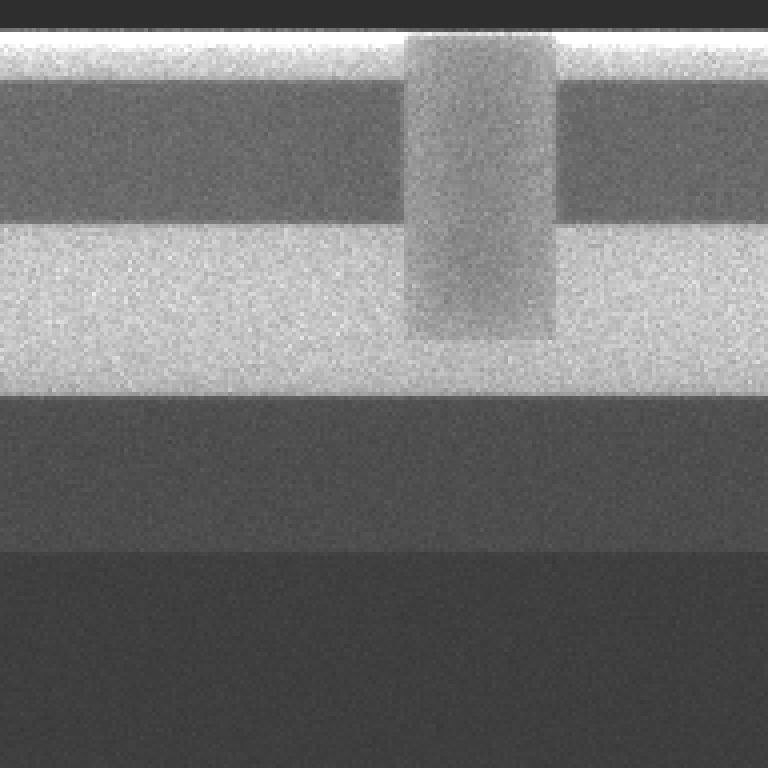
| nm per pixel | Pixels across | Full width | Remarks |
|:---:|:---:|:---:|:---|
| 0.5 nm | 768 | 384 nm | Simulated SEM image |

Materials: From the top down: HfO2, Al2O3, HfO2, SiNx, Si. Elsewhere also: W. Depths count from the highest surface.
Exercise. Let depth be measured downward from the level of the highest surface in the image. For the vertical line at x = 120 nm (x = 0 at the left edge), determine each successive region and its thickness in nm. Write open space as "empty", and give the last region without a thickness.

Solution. HfO2 24, Al2O3 72, HfO2 86, SiNx 78, Si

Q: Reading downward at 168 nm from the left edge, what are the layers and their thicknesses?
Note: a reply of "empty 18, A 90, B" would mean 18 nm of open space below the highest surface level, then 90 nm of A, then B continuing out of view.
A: HfO2 24, Al2O3 72, HfO2 86, SiNx 78, Si